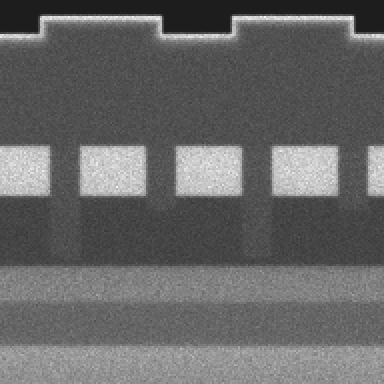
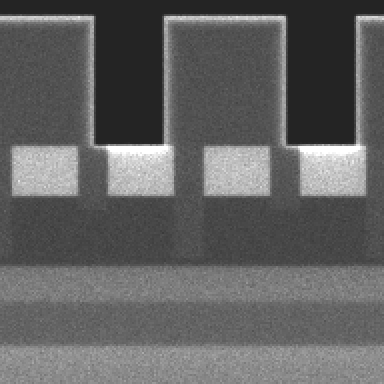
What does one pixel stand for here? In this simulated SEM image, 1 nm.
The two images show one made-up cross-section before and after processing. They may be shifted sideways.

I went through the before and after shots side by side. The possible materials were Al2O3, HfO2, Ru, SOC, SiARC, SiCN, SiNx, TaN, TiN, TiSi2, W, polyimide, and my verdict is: removed, SOC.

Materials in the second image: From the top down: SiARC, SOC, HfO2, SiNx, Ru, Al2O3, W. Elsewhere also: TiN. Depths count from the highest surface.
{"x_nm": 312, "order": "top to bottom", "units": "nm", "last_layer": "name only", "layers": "empty 130, HfO2 50, SiNx 70, Ru 36, Al2O3 44, W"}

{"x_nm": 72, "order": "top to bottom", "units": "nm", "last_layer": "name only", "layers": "SiARC 18, SOC 112, HfO2 50, SiNx 70, Ru 36, Al2O3 44, W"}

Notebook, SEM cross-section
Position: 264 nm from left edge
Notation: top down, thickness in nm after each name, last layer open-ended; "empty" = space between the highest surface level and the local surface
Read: SiARC 18, SOC 112, HfO2 50, SiNx 70, Ru 36, Al2O3 44, W